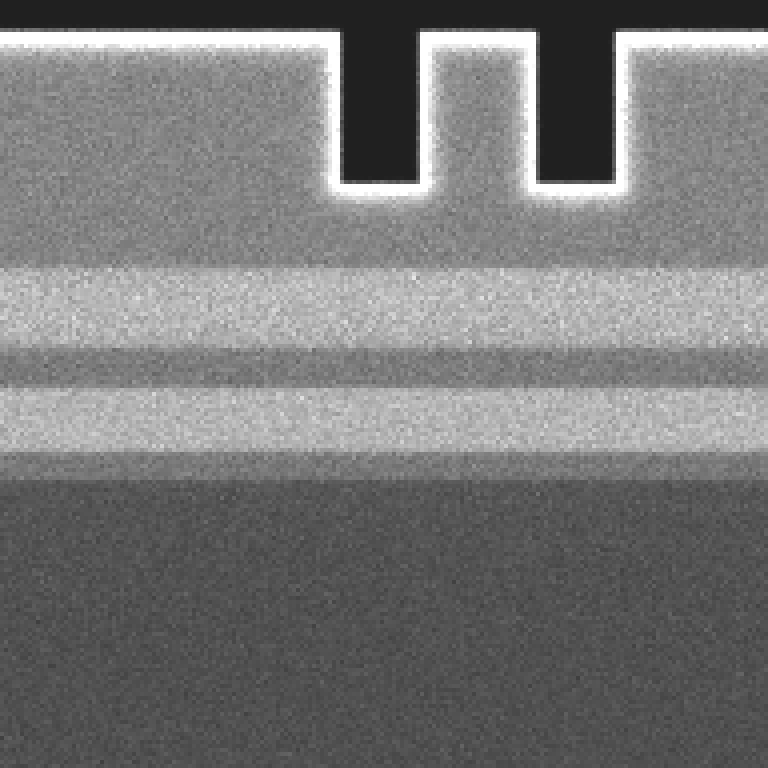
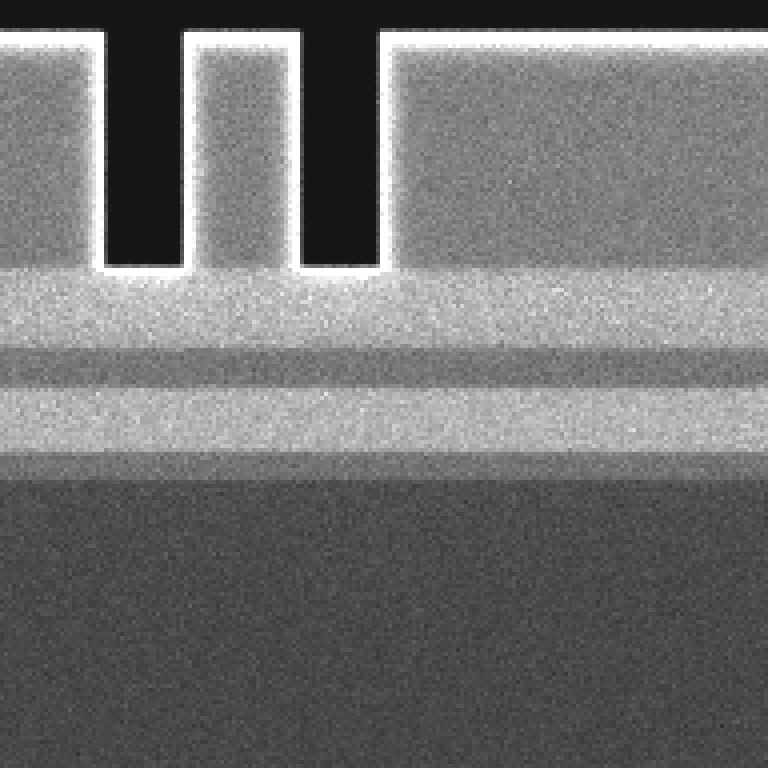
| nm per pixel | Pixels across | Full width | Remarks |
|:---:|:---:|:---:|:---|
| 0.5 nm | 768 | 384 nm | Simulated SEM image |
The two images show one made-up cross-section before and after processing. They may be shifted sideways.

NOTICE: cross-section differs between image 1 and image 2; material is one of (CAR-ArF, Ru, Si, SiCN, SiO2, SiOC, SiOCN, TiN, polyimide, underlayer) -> removed: underlayer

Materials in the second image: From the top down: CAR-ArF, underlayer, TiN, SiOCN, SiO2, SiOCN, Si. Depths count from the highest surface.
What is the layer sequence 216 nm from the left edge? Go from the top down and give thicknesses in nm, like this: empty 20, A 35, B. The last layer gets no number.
CAR-ArF 76, underlayer 42, TiN 40, SiOCN 20, SiO2 32, SiOCN 14, Si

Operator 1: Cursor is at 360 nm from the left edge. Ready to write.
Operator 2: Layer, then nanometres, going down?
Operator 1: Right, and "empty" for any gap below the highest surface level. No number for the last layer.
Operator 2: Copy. CAR-ArF 76, underlayer 42, TiN 40, SiOCN 20, SiO2 32, SiOCN 14, Si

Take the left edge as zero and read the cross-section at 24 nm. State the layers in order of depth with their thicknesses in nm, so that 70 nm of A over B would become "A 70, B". CAR-ArF 76, underlayer 42, TiN 40, SiOCN 20, SiO2 32, SiOCN 14, Si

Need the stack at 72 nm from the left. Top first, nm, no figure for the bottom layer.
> empty 118, TiN 40, SiOCN 20, SiO2 32, SiOCN 14, Si